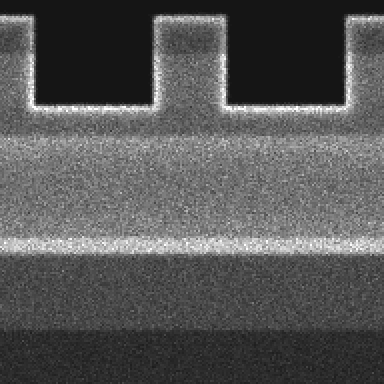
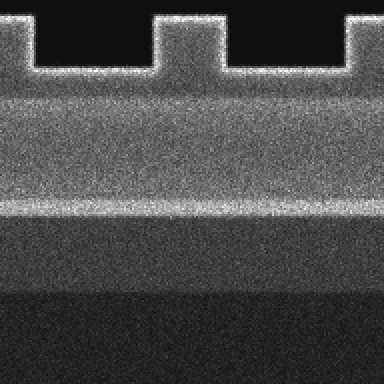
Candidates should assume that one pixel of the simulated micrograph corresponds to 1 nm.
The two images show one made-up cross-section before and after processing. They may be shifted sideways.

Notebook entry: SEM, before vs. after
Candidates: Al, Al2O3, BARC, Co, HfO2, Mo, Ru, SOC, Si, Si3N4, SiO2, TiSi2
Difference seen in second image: SOC removed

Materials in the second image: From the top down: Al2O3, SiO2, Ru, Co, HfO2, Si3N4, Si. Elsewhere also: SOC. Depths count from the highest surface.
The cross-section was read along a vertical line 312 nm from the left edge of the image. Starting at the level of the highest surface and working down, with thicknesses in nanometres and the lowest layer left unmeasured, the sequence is empty 52, SiO2 30, Ru 92, Co 10, HfO2 16, Si3N4 76, Si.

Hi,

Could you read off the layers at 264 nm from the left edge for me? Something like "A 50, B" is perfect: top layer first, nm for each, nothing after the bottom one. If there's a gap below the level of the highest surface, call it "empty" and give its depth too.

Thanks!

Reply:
empty 52, SiO2 30, Ru 92, Co 10, HfO2 16, Si3N4 76, Si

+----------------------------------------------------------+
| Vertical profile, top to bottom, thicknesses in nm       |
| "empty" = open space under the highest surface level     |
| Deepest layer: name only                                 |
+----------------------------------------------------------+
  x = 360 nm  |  Al2O3 52, SiO2 30, Ru 92, Co 10, HfO2 16, Si3N4 76, Si